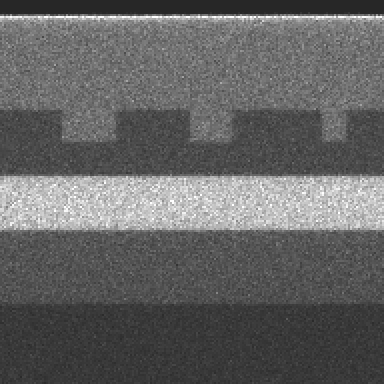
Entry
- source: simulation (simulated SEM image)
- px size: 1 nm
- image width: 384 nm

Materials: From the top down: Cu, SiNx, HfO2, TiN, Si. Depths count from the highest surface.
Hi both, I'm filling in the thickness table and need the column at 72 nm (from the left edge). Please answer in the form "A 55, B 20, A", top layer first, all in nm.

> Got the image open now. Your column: Cu 126, SiNx 34, HfO2 54, TiN 74, Si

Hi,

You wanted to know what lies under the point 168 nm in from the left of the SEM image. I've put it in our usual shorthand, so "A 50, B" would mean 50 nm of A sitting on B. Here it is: Cu 94, SiNx 66, HfO2 54, TiN 74, Si